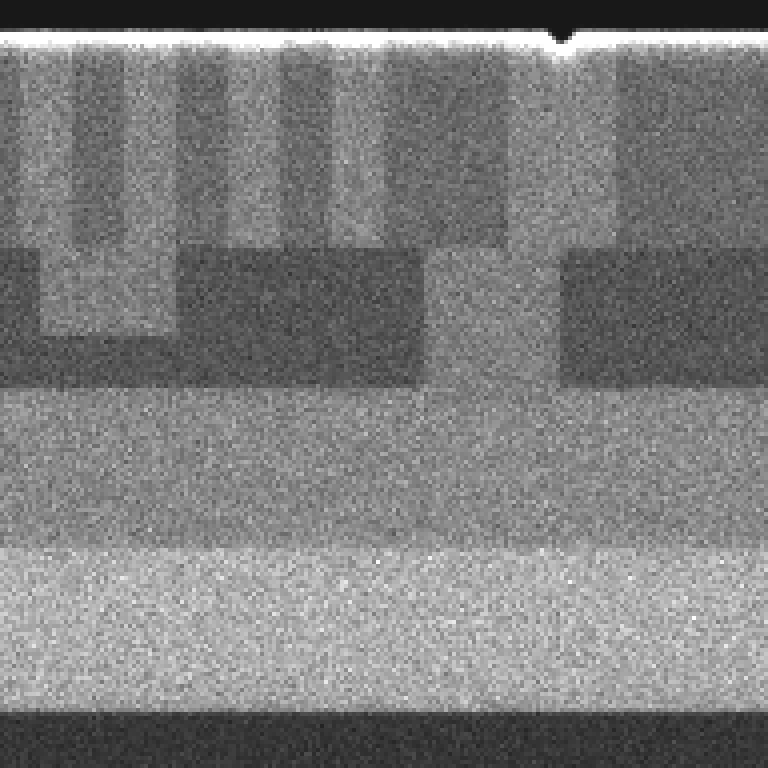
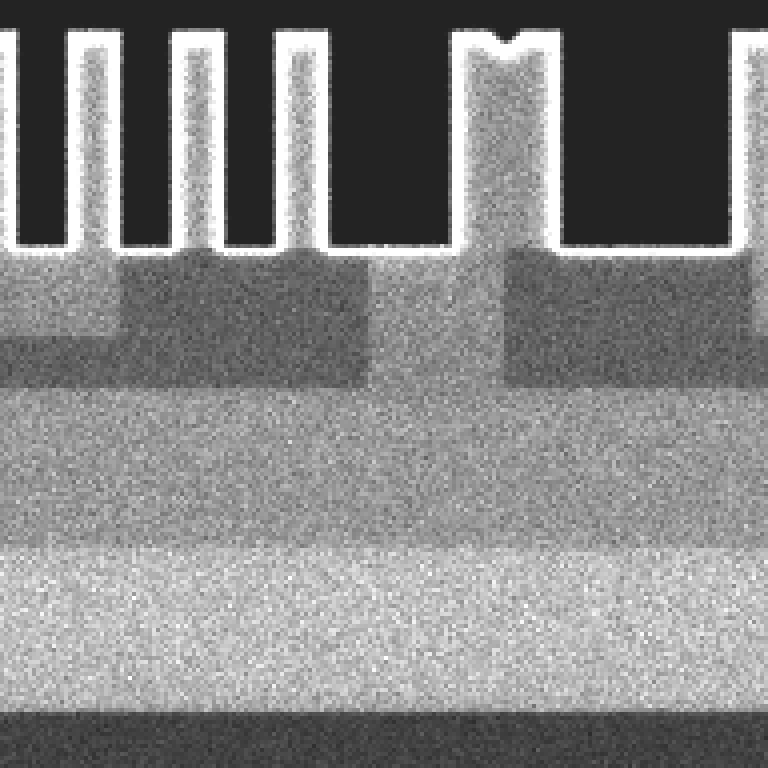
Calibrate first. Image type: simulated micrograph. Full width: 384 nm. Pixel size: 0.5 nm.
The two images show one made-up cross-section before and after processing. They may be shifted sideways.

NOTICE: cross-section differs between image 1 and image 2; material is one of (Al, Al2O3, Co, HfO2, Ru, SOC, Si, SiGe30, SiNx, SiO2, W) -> removed: SOC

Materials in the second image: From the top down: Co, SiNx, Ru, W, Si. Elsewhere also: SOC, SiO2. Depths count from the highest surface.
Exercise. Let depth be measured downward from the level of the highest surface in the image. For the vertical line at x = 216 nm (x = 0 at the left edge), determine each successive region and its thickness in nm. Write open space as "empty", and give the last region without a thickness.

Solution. empty 108, Co 78, Ru 72, W 82, Si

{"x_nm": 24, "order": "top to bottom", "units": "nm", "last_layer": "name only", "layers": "empty 108, Co 44, SiNx 26, Ru 80, W 82, Si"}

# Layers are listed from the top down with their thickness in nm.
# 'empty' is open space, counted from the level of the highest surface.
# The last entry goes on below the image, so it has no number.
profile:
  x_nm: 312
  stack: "empty 108, SiNx 70, Ru 80, W 82, Si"